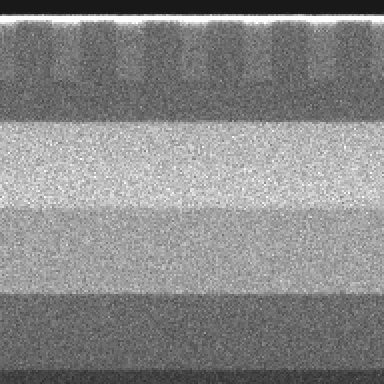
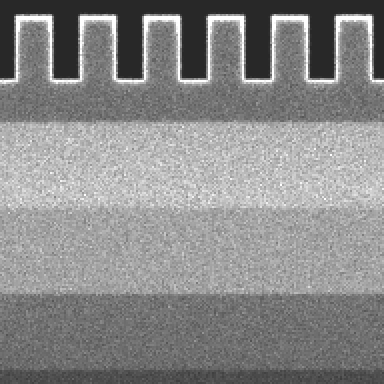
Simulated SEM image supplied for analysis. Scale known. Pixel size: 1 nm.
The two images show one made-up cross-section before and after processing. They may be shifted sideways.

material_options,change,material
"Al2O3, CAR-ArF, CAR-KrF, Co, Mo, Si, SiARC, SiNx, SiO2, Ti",removed,SiARC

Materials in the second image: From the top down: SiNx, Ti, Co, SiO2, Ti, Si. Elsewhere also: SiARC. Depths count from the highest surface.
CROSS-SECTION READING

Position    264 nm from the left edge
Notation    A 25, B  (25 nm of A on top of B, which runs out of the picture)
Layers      empty 64, Ti 42, Co 86, SiO2 86, Ti 76, Si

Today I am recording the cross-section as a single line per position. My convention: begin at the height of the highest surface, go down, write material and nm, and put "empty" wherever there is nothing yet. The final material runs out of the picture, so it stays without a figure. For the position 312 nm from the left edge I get empty 64, Ti 42, Co 86, SiO2 86, Ti 76, Si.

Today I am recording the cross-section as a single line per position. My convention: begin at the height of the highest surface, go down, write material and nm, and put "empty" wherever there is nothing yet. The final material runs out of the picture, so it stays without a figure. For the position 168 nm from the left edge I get SiNx 16, Ti 90, Co 86, SiO2 86, Ti 76, Si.